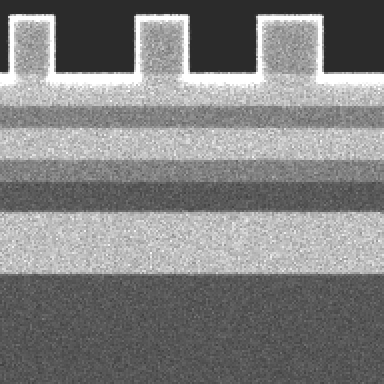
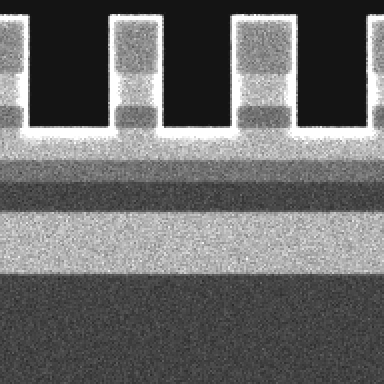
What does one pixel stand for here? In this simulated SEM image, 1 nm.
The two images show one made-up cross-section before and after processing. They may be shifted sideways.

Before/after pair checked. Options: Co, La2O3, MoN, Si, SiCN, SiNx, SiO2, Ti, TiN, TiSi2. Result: removed SiNx and SiO2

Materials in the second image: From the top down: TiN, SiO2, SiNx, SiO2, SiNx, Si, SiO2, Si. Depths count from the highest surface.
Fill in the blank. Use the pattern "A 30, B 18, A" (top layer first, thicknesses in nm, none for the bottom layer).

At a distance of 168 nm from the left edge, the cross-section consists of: empty 112, SiO2 32, SiNx 22, Si 30, SiO2 62, Si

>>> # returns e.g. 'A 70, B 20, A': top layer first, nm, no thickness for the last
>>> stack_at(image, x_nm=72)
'empty 112, SiO2 32, SiNx 22, Si 30, SiO2 62, Si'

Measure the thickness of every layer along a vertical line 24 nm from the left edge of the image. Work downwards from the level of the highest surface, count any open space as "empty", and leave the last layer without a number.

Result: TiN 58, SiO2 32, SiNx 22, SiO2 32, SiNx 22, Si 30, SiO2 62, Si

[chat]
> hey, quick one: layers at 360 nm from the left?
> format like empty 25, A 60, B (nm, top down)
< empty 112, SiO2 32, SiNx 22, Si 30, SiO2 62, Si